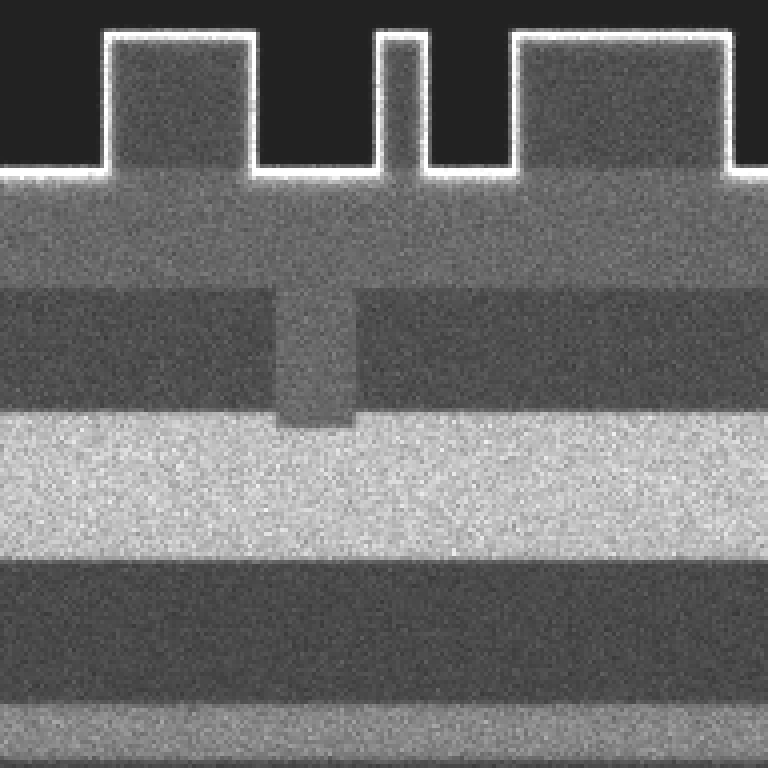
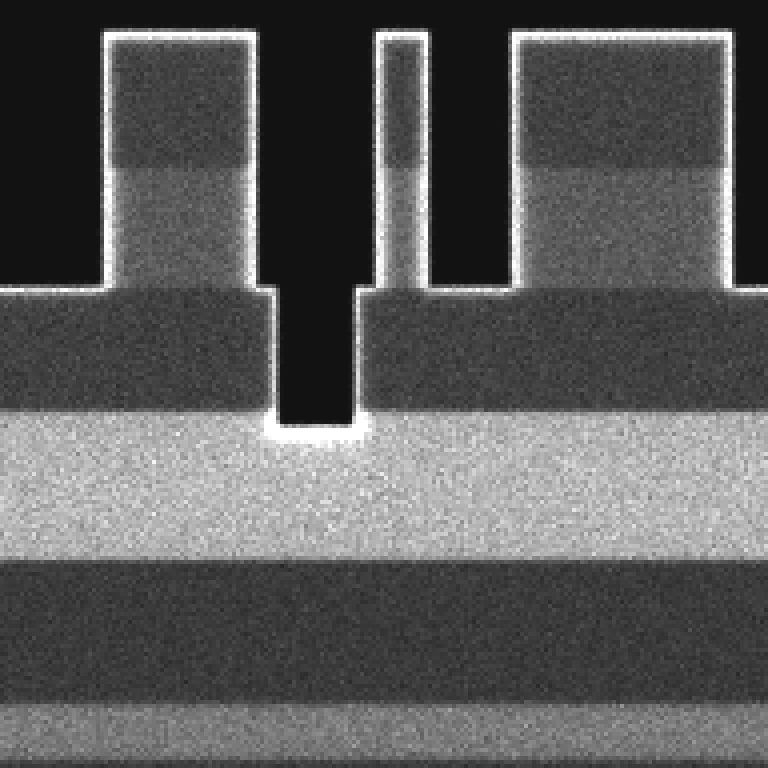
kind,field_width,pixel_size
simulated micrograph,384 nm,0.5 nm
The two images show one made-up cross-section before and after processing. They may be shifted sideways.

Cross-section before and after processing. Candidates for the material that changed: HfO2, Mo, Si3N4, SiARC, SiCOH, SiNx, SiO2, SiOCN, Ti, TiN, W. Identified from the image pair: SiO2 (removed).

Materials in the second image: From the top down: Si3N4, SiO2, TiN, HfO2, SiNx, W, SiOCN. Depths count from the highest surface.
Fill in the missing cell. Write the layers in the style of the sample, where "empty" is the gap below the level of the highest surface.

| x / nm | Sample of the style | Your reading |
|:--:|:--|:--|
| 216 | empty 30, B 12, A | empty 128, TiN 62, HfO2 74, SiNx 72, W 28, SiOCN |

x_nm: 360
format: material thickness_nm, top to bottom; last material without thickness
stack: Si3N4 68, SiO2 60, TiN 62, HfO2 74, SiNx 72, W 28, SiOCN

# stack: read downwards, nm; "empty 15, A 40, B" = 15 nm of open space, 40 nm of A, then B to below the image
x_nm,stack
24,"empty 128, TiN 62, HfO2 74, SiNx 72, W 28, SiOCN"